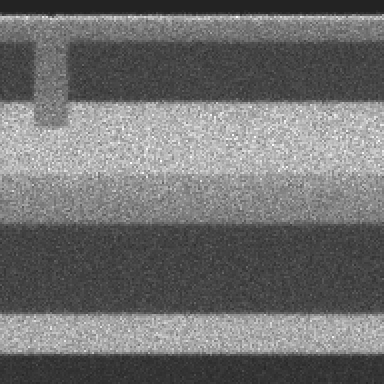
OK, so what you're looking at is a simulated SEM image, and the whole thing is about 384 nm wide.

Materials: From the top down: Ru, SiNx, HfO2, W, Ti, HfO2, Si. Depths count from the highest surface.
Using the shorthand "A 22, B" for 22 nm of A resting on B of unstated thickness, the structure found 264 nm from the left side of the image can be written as Ru 26, SiNx 60, HfO2 72, W 50, Ti 90, HfO2 40, Si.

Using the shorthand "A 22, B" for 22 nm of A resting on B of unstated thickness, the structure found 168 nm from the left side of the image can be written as Ru 26, SiNx 60, HfO2 72, W 50, Ti 90, HfO2 40, Si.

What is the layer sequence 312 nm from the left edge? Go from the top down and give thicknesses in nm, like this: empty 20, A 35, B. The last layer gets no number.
Ru 26, SiNx 60, HfO2 72, W 50, Ti 90, HfO2 40, Si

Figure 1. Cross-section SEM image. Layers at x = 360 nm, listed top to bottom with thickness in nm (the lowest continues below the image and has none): Ru 26, SiNx 60, HfO2 72, W 50, Ti 90, HfO2 40, Si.